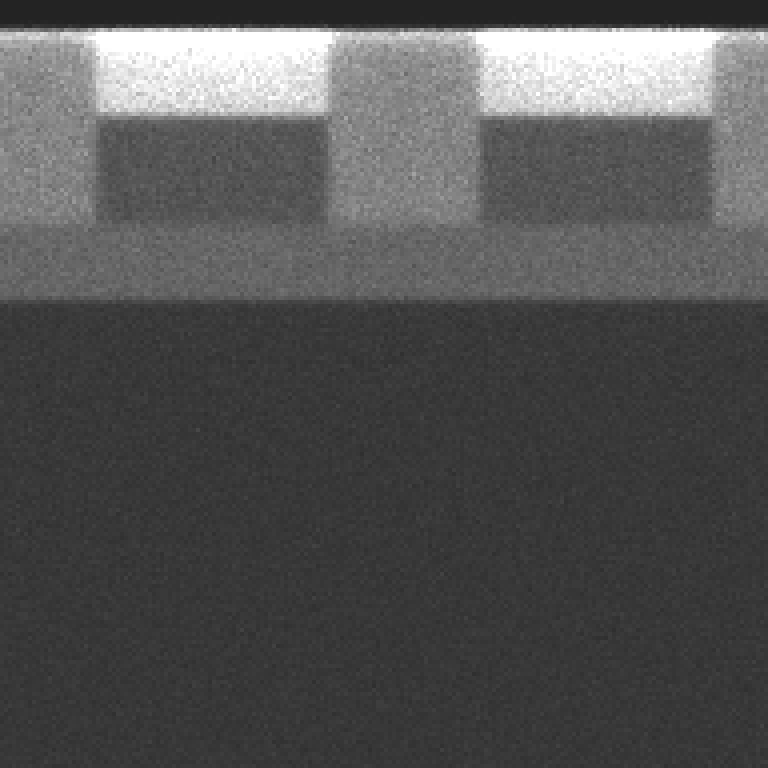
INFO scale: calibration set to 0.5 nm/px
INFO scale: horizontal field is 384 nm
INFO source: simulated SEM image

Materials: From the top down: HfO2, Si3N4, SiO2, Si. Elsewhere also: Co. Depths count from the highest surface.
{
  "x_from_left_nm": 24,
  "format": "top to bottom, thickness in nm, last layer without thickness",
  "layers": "Co 96, SiO2 38, Si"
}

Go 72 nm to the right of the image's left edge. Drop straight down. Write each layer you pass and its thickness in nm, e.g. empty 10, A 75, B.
HfO2 42, Si3N4 54, SiO2 38, Si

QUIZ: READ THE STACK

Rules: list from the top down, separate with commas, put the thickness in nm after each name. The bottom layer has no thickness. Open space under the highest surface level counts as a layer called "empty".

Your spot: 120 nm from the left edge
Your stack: HfO2 42, Si3N4 54, SiO2 38, Si